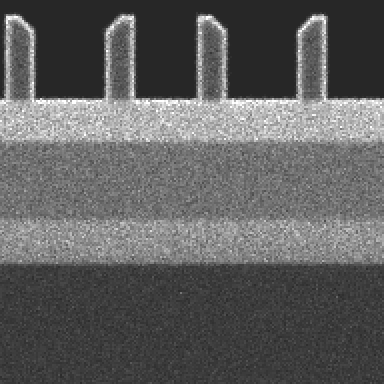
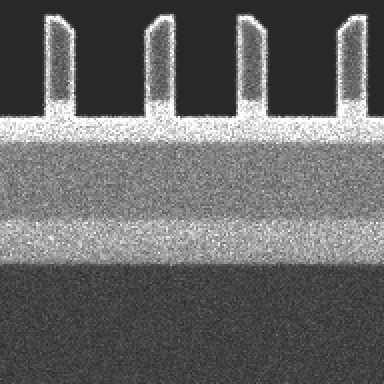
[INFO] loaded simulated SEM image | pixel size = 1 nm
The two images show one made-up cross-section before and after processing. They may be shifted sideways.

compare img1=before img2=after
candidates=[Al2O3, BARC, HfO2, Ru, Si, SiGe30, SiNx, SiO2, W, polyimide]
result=removed:W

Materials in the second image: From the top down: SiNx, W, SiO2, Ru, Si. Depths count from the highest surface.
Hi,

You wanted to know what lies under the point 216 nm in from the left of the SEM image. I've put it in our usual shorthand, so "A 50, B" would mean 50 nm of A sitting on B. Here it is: empty 102, W 24, SiO2 78, Ru 44, Si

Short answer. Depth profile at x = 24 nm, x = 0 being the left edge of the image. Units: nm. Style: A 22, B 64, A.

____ empty 102, W 24, SiO2 78, Ru 44, Si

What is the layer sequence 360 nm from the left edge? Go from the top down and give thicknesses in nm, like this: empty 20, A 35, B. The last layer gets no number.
SiNx 84, W 42, SiO2 78, Ru 44, Si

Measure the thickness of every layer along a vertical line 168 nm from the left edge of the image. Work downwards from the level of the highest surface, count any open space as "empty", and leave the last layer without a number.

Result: SiNx 84, W 42, SiO2 78, Ru 44, Si